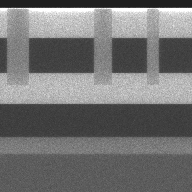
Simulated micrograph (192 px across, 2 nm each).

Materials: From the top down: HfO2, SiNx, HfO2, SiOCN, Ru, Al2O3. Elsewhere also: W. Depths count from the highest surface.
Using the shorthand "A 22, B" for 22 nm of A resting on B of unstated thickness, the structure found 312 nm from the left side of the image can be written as W 154, HfO2 38, SiOCN 66, Ru 34, Al2O3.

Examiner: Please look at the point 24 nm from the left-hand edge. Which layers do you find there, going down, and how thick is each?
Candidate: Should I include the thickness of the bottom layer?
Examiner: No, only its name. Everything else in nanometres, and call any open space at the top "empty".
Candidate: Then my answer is W 154, HfO2 38, SiOCN 66, Ru 34, Al2O3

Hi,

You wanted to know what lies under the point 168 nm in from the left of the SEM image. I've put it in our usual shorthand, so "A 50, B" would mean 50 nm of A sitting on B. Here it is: HfO2 60, SiNx 70, HfO2 62, SiOCN 66, Ru 34, Al2O3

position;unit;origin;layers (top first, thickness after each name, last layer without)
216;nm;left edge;W 154, HfO2 38, SiOCN 66, Ru 34, Al2O3